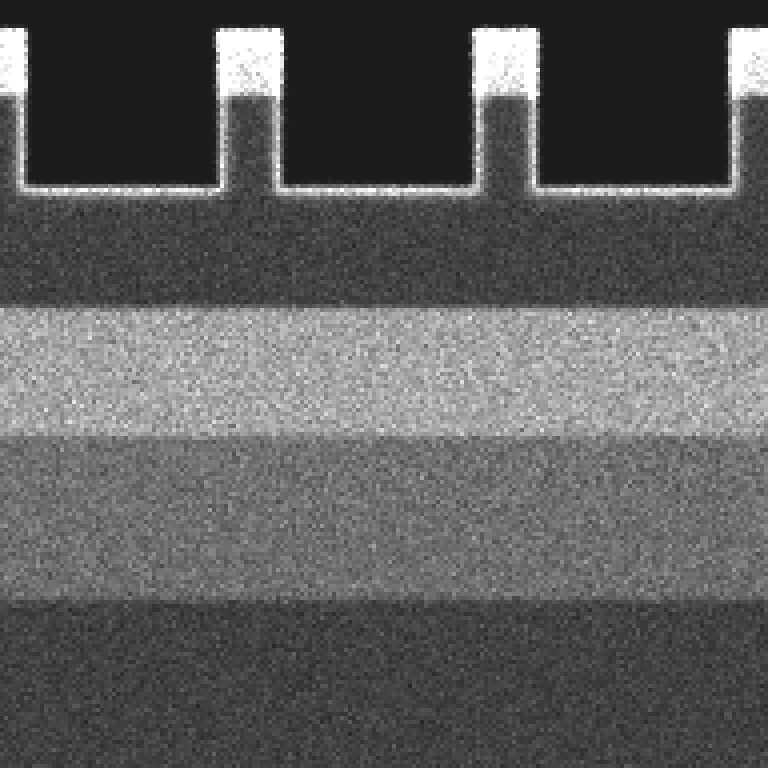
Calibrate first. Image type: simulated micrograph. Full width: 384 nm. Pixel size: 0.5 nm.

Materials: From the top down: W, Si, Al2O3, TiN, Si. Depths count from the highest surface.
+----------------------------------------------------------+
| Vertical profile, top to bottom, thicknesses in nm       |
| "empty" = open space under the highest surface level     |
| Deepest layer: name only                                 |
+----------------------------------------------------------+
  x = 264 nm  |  W 32, Si 106, Al2O3 64, TiN 82, Si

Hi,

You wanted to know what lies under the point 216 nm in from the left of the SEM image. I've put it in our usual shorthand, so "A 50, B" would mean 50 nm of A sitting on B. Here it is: empty 78, Si 60, Al2O3 64, TiN 82, Si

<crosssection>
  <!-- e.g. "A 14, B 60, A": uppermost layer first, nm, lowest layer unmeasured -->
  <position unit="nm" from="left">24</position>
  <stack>empty 78, Si 60, Al2O3 64, TiN 82, Si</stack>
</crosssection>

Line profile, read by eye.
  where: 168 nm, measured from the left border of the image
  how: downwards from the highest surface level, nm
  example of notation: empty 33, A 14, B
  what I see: empty 78, Si 60, Al2O3 64, TiN 82, Si